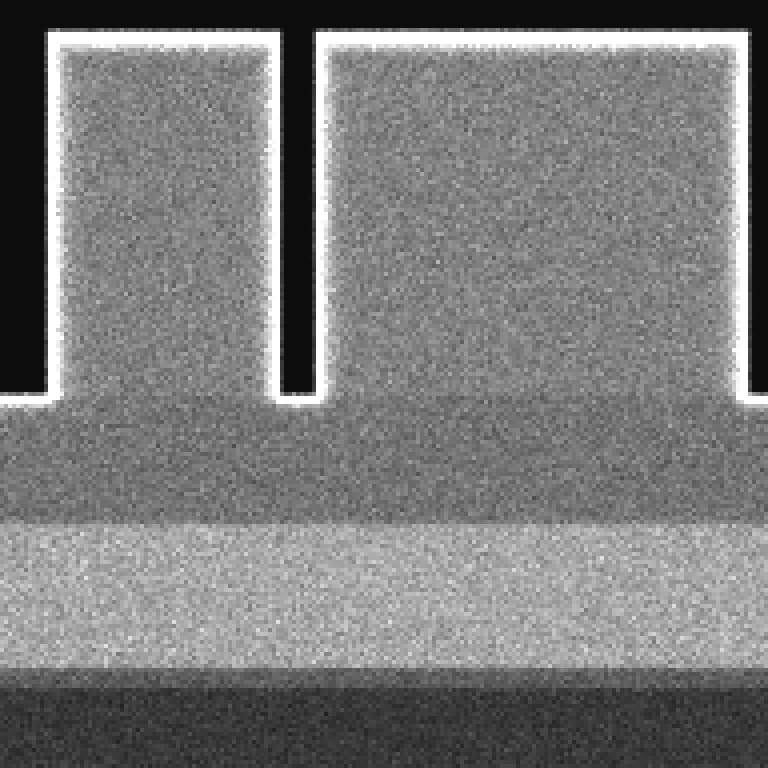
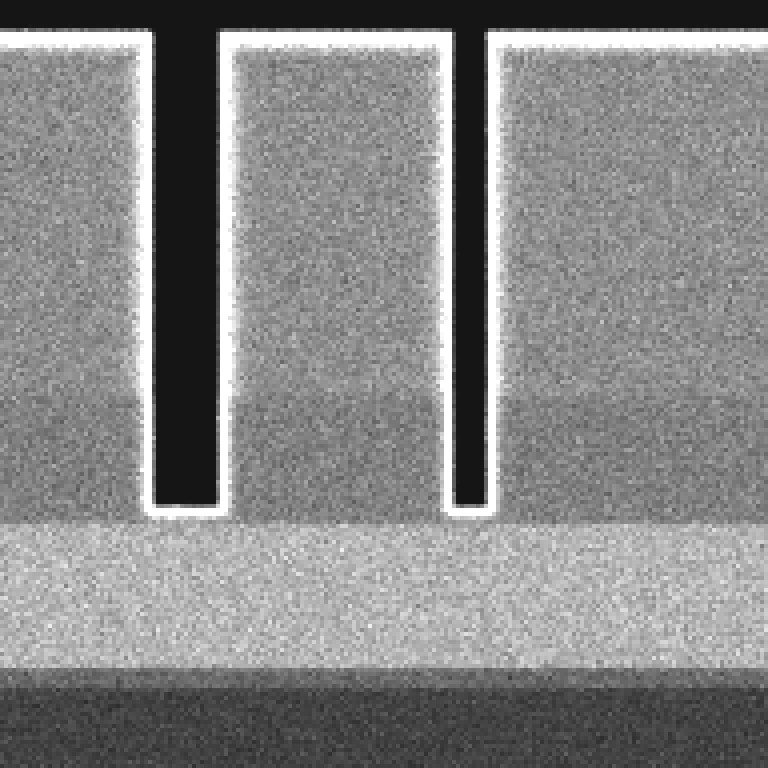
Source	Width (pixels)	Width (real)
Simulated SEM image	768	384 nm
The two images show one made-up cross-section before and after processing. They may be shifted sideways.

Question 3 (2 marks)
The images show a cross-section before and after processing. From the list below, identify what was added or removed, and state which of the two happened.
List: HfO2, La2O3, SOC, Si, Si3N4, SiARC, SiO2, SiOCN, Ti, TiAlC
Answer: Si3N4 was removed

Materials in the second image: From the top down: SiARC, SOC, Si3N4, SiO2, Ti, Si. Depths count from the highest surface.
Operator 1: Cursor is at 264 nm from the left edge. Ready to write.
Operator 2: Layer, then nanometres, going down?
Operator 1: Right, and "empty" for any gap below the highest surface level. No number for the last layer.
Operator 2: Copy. SiARC 18, SOC 164, Si3N4 64, SiO2 72, Ti 10, Si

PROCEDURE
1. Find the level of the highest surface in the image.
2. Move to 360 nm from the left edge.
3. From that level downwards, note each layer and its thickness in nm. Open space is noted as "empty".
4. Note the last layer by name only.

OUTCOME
SiARC 18, SOC 164, Si3N4 64, SiO2 72, Ti 10, Si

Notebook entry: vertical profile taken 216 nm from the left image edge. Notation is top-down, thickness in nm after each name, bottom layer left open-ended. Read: SiARC 18, SOC 164, Si3N4 64, SiO2 72, Ti 10, Si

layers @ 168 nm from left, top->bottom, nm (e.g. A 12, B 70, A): SiARC 18, SOC 164, Si3N4 64, SiO2 72, Ti 10, Si